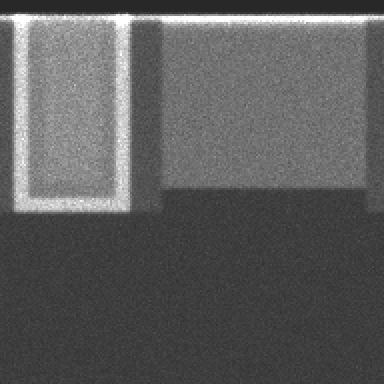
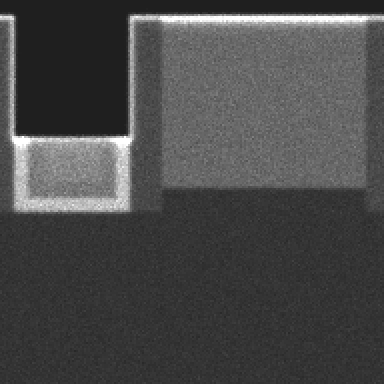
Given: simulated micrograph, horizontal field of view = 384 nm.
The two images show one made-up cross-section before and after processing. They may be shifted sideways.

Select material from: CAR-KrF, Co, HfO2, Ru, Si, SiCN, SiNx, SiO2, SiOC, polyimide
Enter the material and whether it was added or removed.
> Co and HfO2 and Ru / removed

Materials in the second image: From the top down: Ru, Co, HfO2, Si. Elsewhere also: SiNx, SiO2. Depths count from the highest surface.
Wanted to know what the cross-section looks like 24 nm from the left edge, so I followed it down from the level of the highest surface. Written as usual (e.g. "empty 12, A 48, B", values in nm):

empty 122, HfO2 74, Si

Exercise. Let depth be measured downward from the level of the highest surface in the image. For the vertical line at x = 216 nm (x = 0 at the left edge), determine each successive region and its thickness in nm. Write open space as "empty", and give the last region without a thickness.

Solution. SiO2 172, Si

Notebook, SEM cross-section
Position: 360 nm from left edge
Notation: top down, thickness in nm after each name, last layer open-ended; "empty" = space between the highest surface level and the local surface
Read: SiO2 172, Si